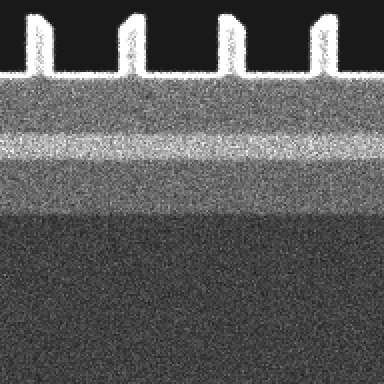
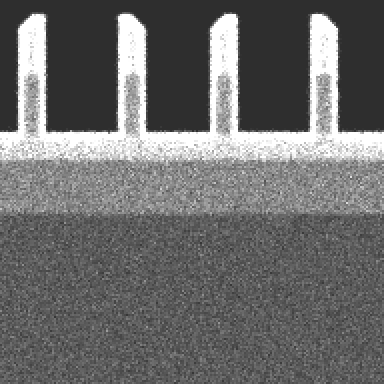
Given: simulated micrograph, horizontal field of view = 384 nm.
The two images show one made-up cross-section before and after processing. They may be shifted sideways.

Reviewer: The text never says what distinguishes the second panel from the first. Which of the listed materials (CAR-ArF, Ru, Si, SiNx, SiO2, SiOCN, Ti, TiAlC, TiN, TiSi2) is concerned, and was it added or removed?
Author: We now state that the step removed TiN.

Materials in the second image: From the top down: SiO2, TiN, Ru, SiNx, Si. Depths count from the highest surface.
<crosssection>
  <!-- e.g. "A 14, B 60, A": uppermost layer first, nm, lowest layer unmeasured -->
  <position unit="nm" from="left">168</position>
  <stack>empty 118, Ru 26, SiNx 54, Si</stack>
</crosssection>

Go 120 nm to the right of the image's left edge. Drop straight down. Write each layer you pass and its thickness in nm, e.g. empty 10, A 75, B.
SiO2 58, TiN 60, Ru 26, SiNx 54, Si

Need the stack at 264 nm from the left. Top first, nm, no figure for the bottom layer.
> empty 118, Ru 26, SiNx 54, Si